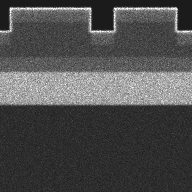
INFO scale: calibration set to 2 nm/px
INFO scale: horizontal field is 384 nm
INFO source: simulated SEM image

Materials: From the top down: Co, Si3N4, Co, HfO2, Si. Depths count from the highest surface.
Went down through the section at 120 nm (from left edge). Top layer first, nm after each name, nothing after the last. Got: Co 28, Si3N4 70, Co 30, HfO2 66, Si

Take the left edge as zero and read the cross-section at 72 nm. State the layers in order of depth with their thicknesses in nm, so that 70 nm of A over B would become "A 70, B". Co 28, Si3N4 70, Co 30, HfO2 66, Si